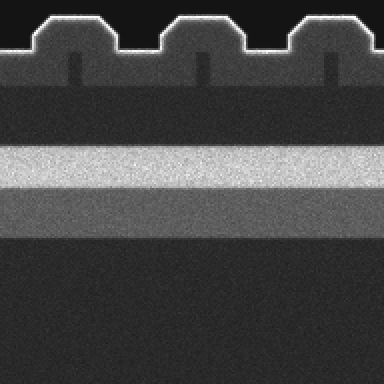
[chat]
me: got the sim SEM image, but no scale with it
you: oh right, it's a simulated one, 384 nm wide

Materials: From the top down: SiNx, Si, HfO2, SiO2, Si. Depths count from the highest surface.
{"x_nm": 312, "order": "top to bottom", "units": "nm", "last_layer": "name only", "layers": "SiNx 70, Si 60, HfO2 42, SiO2 50, Si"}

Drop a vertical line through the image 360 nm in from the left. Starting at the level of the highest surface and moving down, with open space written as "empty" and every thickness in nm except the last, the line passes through empty 6, SiNx 64, Si 60, HfO2 42, SiO2 50, Si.